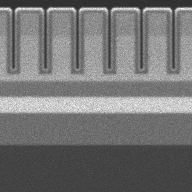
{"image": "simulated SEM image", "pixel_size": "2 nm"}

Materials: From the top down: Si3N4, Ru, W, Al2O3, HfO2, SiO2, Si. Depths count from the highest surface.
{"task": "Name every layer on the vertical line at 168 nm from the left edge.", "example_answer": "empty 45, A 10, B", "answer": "Si3N4 10, Ru 46, W 90, Al2O3 32, HfO2 32, SiO2 64, Si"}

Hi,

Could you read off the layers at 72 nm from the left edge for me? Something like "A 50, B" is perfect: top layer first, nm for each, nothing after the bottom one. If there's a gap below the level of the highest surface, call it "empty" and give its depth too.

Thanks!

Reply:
Si3N4 10, Ru 46, W 90, Al2O3 32, HfO2 32, SiO2 64, Si